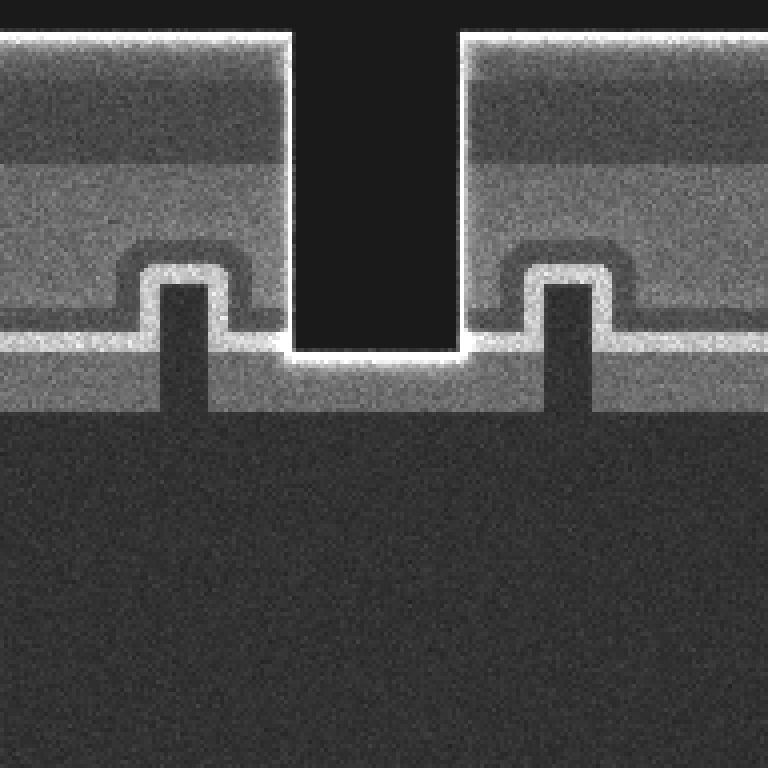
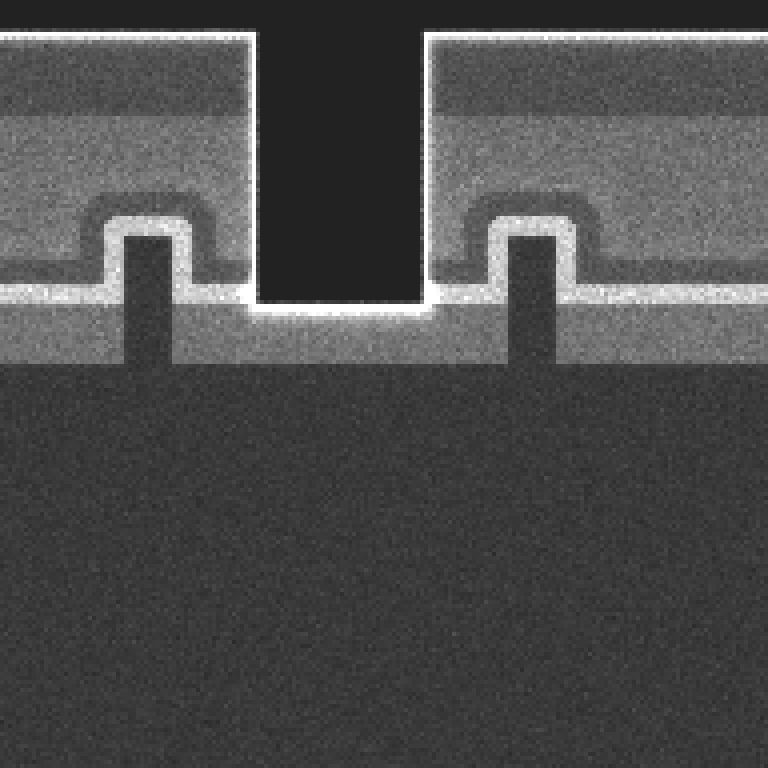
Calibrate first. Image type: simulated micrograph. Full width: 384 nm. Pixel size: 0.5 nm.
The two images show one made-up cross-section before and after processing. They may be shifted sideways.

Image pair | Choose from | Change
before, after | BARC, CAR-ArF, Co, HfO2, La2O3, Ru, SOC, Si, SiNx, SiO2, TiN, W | SOC (removed)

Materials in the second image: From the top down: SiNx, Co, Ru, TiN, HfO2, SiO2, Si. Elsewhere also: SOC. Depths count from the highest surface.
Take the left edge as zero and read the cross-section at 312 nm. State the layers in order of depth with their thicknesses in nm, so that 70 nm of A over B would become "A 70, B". SiNx 42, Co 62, Ru 10, TiN 12, HfO2 10, SiO2 30, Si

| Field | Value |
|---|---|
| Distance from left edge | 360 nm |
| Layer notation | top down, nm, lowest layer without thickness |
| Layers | SiNx 42, Co 62, Ru 10, TiN 12, HfO2 10, SiO2 30, Si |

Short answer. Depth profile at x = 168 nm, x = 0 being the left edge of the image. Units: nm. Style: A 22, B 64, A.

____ empty 136, SiO2 30, Si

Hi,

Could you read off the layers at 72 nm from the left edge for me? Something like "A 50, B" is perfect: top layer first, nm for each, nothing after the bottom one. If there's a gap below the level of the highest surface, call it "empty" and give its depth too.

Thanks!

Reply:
SiNx 42, Co 28, Ru 10, TiN 12, HfO2 10, Si